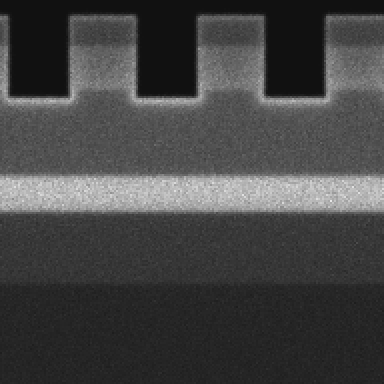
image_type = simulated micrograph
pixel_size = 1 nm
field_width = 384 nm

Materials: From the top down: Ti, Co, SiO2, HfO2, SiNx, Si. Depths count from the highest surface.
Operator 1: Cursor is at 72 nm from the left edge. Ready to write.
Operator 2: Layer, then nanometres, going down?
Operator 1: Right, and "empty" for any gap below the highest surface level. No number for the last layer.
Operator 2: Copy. Ti 30, Co 44, SiO2 86, HfO2 36, SiNx 72, Si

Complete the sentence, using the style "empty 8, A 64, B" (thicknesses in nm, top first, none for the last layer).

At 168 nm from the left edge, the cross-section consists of empty 82, SiO2 78, HfO2 36, SiNx 72, Si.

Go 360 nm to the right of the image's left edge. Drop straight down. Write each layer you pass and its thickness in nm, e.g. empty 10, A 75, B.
Ti 30, Co 44, SiO2 86, HfO2 36, SiNx 72, Si